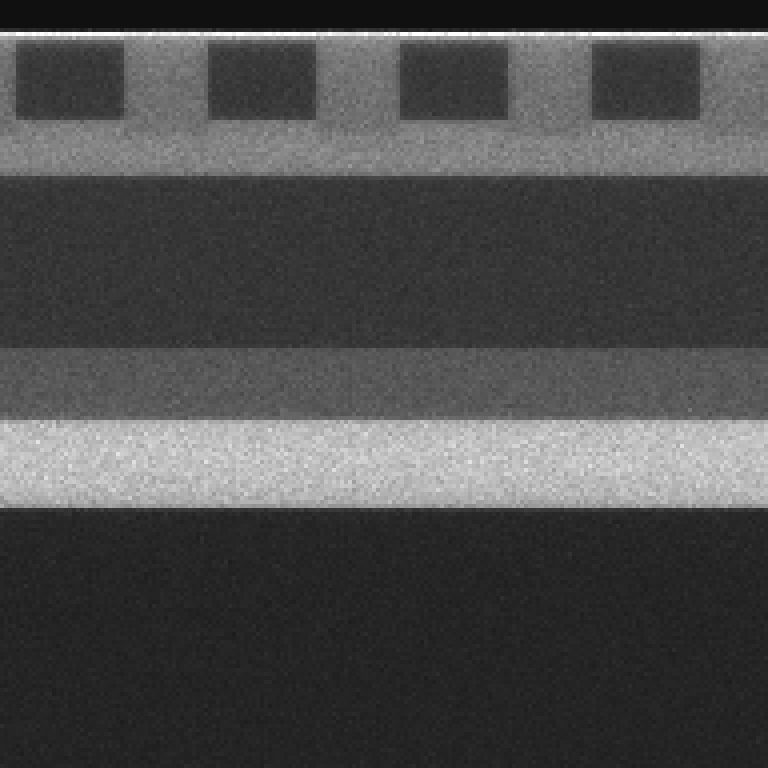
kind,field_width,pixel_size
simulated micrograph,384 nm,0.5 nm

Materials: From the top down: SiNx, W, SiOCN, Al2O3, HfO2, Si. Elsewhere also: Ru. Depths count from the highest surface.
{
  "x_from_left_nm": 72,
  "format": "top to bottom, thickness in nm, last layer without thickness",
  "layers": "Ru 52, W 20, SiOCN 86, Al2O3 36, HfO2 44, Si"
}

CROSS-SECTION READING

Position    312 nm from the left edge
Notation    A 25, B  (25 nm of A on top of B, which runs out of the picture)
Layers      SiNx 44, W 28, SiOCN 86, Al2O3 36, HfO2 44, Si